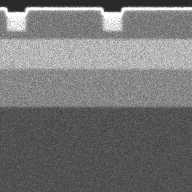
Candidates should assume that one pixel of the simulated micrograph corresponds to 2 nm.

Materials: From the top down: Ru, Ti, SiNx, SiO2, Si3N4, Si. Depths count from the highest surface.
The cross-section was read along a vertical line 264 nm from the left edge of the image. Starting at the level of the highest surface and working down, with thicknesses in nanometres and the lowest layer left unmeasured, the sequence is Ti 6, SiNx 56, SiO2 60, Si3N4 76, Si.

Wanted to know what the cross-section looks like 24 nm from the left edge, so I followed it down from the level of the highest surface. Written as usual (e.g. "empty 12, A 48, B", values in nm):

empty 10, Ru 36, Ti 6, SiNx 10, SiO2 60, Si3N4 76, Si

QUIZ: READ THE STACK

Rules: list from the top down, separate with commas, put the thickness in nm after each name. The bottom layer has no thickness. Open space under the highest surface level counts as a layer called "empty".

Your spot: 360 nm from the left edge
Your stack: Ti 6, SiNx 56, SiO2 60, Si3N4 76, Si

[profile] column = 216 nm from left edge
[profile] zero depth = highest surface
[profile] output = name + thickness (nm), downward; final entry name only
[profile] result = empty 10, Ru 36, Ti 6, SiNx 10, SiO2 60, Si3N4 76, Si